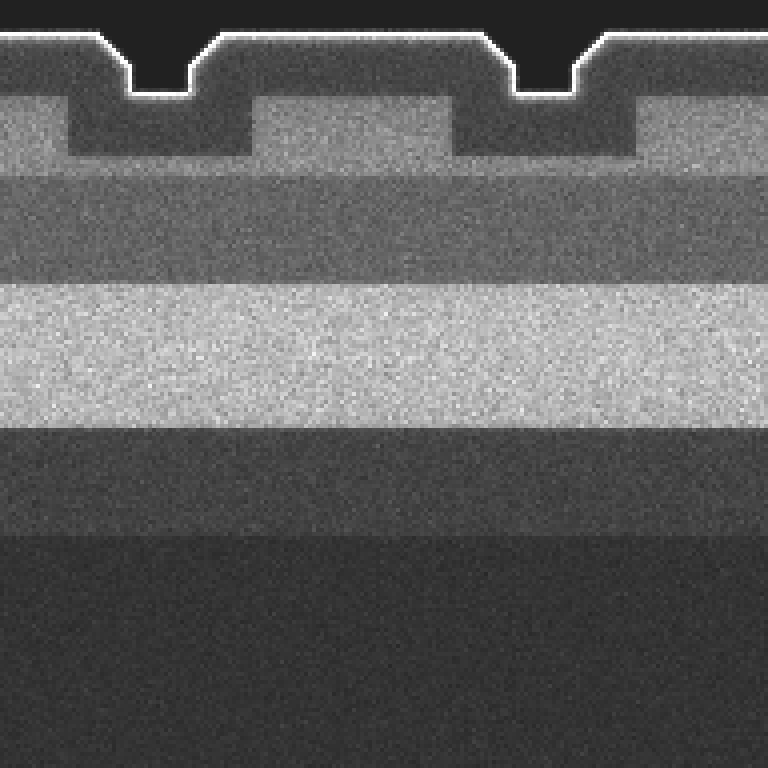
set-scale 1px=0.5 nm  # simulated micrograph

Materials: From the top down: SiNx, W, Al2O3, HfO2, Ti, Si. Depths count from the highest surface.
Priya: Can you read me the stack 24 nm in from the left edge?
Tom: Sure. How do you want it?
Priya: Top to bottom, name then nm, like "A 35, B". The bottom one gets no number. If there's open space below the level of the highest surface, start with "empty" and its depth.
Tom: SiNx 32, W 40, Al2O3 54, HfO2 72, Ti 54, Si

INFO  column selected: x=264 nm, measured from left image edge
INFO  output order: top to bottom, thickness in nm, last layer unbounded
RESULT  empty 30, SiNx 32, W 10, Al2O3 54, HfO2 72, Ti 54, Si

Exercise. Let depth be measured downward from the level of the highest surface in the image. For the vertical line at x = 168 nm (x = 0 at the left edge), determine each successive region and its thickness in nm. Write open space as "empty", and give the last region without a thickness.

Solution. SiNx 32, W 40, Al2O3 54, HfO2 72, Ti 54, Si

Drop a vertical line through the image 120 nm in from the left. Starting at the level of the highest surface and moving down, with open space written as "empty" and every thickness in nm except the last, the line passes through SiNx 62, W 10, Al2O3 54, HfO2 72, Ti 54, Si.